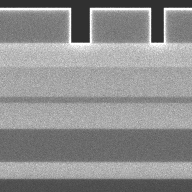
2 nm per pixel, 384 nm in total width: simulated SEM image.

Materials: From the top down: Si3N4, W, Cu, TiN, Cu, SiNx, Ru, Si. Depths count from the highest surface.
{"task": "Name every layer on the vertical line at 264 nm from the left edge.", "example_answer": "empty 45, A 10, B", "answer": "Si3N4 70, W 48, Cu 60, TiN 12, Cu 52, SiNx 66, Ru 34, Si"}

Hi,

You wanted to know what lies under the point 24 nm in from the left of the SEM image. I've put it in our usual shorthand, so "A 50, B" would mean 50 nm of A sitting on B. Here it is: Si3N4 70, W 48, Cu 60, TiN 12, Cu 52, SiNx 66, Ru 34, Si